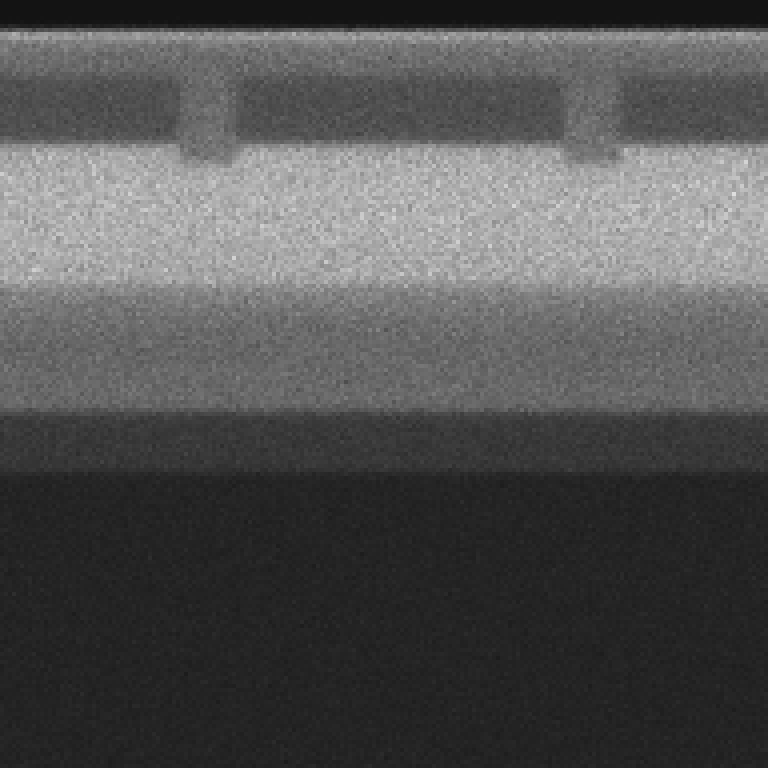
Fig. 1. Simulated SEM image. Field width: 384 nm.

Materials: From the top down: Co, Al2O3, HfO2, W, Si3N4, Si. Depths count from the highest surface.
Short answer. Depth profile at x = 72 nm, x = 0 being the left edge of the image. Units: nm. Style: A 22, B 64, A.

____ Co 22, Al2O3 34, HfO2 70, W 64, Si3N4 30, Si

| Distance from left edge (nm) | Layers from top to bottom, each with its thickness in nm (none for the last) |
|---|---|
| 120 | Co 22, Al2O3 34, HfO2 70, W 64, Si3N4 30, Si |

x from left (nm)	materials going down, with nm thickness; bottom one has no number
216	Co 22, Al2O3 34, HfO2 70, W 64, Si3N4 30, Si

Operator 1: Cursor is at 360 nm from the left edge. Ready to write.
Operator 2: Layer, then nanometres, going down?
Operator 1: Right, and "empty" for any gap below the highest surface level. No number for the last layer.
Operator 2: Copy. Co 22, Al2O3 34, HfO2 70, W 64, Si3N4 30, Si